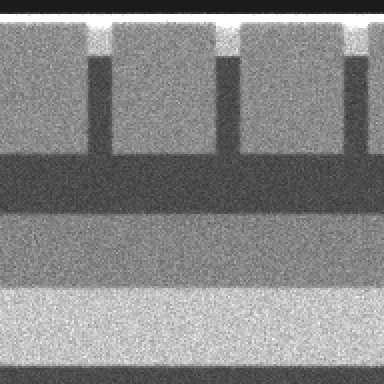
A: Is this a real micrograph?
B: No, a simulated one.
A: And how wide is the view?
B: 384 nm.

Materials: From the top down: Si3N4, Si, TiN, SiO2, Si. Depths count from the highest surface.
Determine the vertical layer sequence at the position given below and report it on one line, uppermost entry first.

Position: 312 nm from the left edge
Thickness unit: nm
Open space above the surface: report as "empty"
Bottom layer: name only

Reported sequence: Si3N4 138, Si 60, TiN 74, SiO2 78, Si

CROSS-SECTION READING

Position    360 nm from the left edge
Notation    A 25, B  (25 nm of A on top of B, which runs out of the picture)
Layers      SiO2 40, Si 158, TiN 74, SiO2 78, Si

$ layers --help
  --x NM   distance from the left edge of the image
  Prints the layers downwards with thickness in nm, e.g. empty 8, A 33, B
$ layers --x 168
Si3N4 138, Si 60, TiN 74, SiO2 78, Si